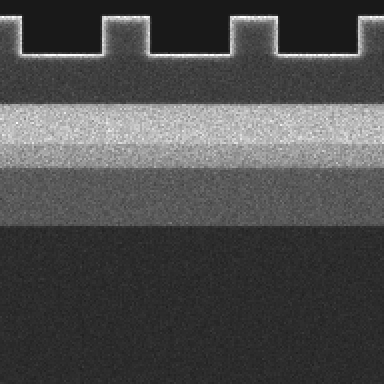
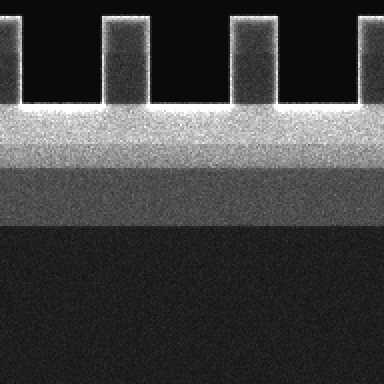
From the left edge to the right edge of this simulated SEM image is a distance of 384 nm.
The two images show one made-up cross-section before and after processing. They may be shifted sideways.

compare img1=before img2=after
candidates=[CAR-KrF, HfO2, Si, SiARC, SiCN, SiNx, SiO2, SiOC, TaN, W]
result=removed:SiNx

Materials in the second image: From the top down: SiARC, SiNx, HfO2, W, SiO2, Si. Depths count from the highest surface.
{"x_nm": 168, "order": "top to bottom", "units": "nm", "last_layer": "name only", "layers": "empty 88, HfO2 40, W 24, SiO2 58, Si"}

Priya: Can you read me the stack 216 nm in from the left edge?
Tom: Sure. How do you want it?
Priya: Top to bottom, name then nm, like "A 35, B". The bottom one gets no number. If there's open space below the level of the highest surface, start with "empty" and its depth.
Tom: empty 88, HfO2 40, W 24, SiO2 58, Si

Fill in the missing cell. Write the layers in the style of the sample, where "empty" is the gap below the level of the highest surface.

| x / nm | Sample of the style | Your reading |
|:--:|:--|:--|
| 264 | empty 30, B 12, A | SiARC 38, SiNx 50, HfO2 40, W 24, SiO2 58, Si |